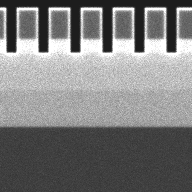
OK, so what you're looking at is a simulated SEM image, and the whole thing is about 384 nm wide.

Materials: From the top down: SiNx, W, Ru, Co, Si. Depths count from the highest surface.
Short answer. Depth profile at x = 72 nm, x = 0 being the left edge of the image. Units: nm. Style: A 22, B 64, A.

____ SiNx 62, W 28, Ru 74, Co 74, Si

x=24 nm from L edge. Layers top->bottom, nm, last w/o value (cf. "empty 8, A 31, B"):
empty 90, Ru 74, Co 74, Si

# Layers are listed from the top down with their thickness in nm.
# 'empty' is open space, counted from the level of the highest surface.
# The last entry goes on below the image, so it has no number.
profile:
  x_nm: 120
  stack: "SiNx 62, W 28, Ru 74, Co 74, Si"